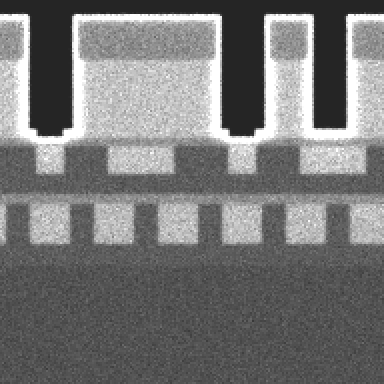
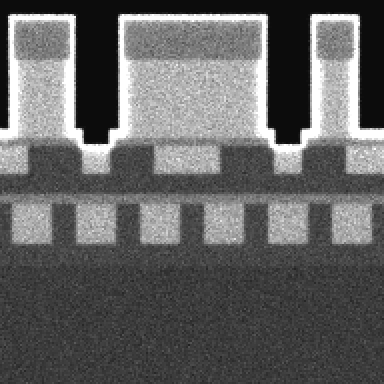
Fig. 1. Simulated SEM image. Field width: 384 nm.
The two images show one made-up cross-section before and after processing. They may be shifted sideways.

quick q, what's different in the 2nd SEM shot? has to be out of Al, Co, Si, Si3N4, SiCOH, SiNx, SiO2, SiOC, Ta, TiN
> Si3N4 removed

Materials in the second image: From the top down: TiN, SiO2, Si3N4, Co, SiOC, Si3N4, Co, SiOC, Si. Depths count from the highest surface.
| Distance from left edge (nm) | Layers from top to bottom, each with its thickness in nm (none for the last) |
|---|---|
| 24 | TiN 44, SiO2 78, Si3N4 8, Co 28, SiOC 20, Si3N4 10, Co 40, SiOC 22, Si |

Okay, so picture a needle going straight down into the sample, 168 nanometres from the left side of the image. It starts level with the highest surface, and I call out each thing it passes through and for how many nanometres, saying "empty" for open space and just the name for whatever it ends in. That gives TiN 44, SiO2 78, Si3N4 8, Co 28, SiOC 20, Si3N4 10, Co 40, SiOC 22, Si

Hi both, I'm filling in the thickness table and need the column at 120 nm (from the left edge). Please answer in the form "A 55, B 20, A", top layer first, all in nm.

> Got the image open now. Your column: TiN 44, SiO2 78, Si3N4 8, SiOC 48, Si3N4 10, SiOC 62, Si